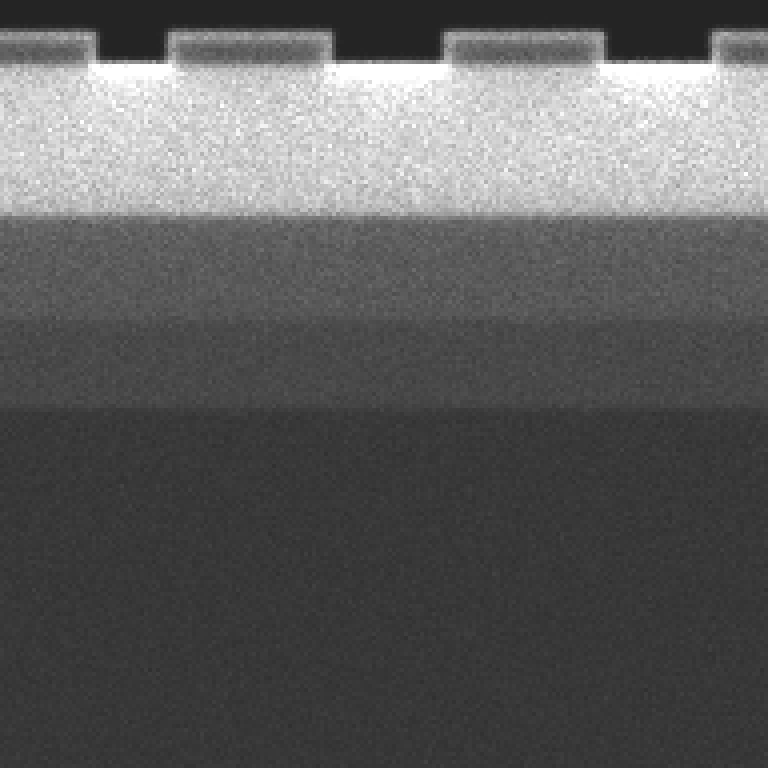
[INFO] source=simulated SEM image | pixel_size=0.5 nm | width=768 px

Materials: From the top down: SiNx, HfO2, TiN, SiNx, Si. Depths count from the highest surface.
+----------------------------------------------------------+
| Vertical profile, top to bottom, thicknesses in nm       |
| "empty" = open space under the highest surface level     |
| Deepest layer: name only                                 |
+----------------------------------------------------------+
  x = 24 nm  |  SiNx 16, HfO2 76, TiN 52, SiNx 44, Si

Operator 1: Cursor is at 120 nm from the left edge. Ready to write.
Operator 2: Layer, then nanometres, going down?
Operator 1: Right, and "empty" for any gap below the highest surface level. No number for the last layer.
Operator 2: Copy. SiNx 16, HfO2 76, TiN 52, SiNx 44, Si